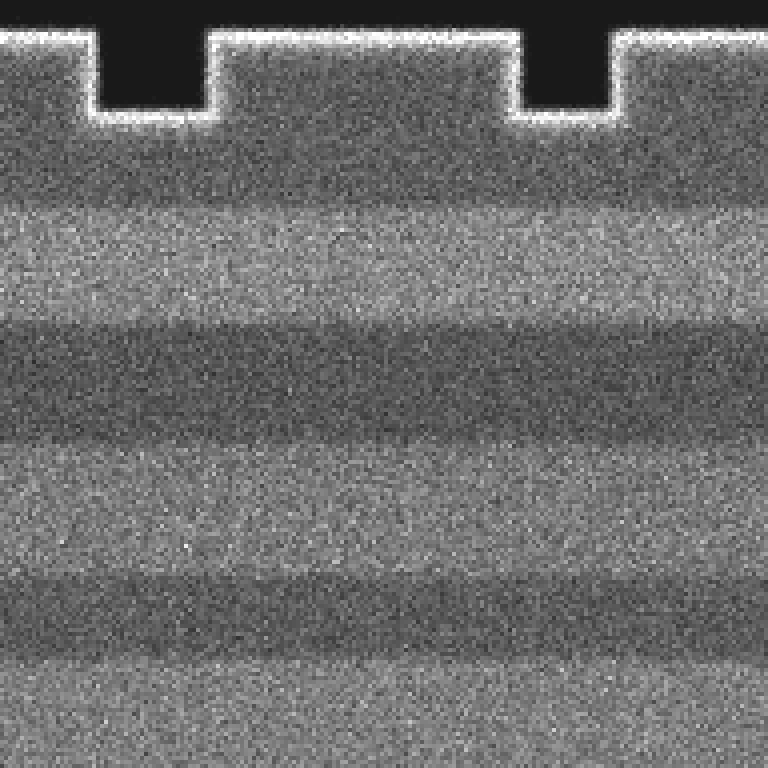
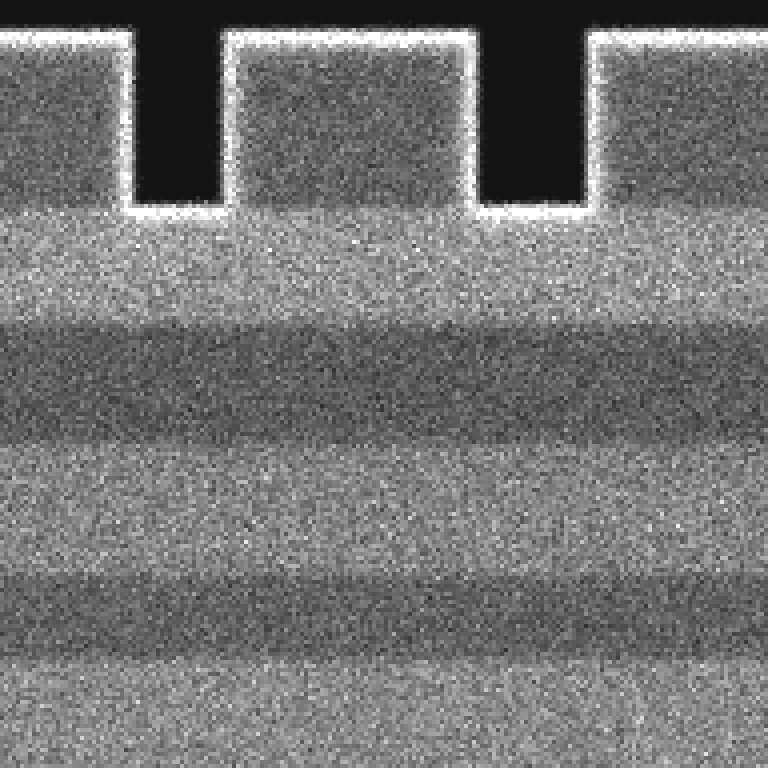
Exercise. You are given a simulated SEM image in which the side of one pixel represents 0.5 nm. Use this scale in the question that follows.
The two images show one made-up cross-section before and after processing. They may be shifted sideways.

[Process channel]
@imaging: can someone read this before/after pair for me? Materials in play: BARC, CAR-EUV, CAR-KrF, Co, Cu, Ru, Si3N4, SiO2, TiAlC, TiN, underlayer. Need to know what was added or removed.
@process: underlayer removed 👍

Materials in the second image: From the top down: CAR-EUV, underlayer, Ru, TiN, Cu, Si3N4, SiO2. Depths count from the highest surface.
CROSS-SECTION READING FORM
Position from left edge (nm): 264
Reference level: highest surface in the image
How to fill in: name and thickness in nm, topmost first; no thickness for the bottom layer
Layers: empty 88, Ru 58, TiN 60, Cu 66, Si3N4 42, SiO2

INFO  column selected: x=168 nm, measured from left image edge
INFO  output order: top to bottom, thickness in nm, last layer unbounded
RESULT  CAR-EUV 40, underlayer 48, Ru 58, TiN 60, Cu 66, Si3N4 42, SiO2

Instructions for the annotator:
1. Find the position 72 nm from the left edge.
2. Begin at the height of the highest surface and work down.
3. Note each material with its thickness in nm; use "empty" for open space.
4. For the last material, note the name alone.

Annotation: empty 88, Ru 58, TiN 60, Cu 66, Si3N4 42, SiO2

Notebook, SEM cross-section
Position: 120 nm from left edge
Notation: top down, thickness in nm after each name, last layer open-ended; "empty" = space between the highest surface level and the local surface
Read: CAR-EUV 40, underlayer 48, Ru 58, TiN 60, Cu 66, Si3N4 42, SiO2